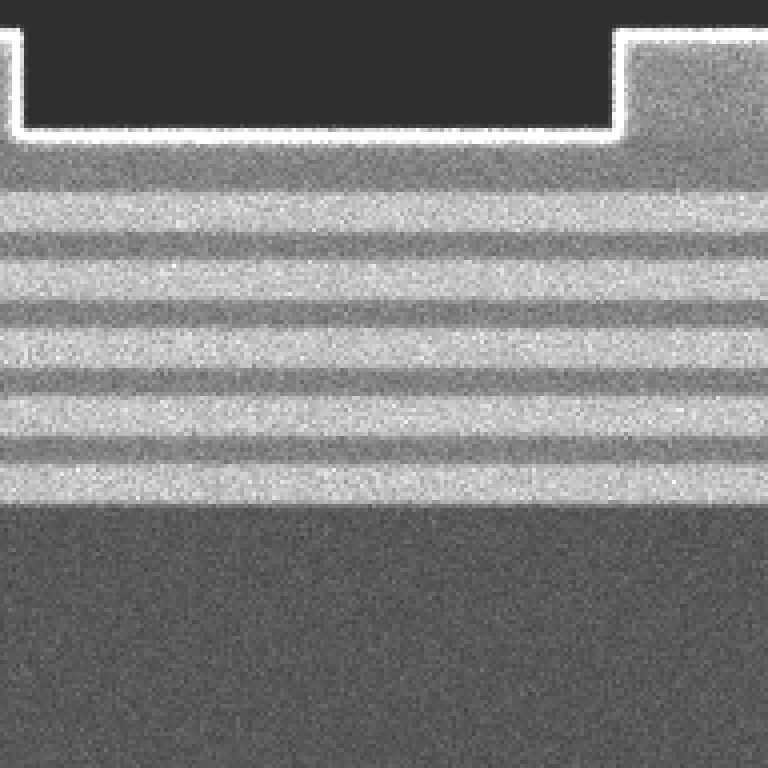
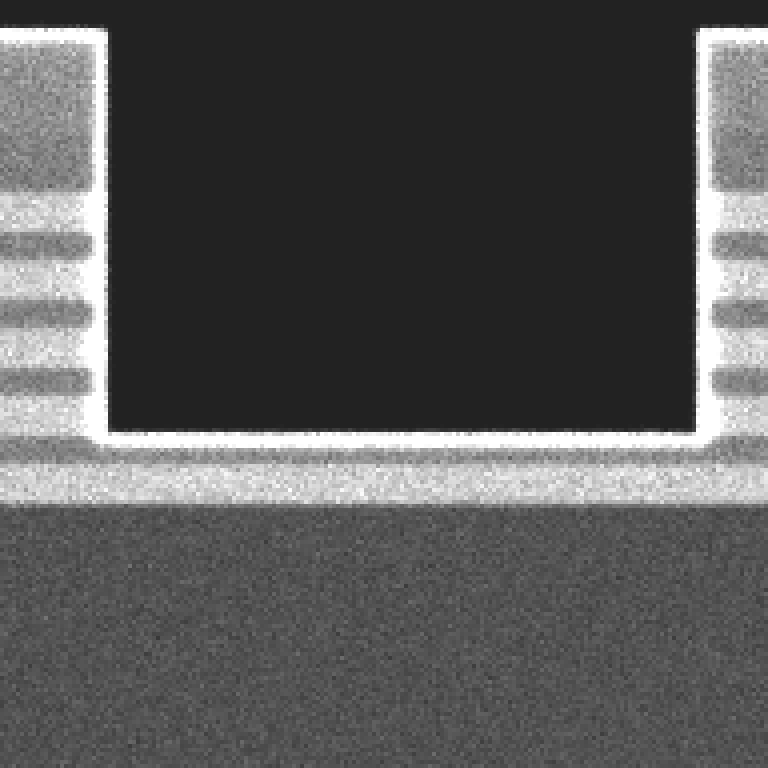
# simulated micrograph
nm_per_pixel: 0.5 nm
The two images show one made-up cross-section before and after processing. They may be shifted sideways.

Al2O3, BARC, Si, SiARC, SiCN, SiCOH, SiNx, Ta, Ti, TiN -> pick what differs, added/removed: Al2O3 and SiNx removed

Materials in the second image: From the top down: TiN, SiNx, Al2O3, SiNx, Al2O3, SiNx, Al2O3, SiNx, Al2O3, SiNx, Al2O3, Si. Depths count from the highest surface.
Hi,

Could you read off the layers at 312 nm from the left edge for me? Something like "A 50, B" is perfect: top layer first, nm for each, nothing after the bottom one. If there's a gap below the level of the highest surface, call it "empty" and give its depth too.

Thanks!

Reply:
empty 202, SiNx 14, Al2O3 20, Si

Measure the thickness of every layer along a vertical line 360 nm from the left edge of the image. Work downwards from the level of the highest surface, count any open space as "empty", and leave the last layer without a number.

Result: TiN 50, SiNx 30, Al2O3 20, SiNx 14, Al2O3 20, SiNx 14, Al2O3 20, SiNx 14, Al2O3 20, SiNx 14, Al2O3 20, Si